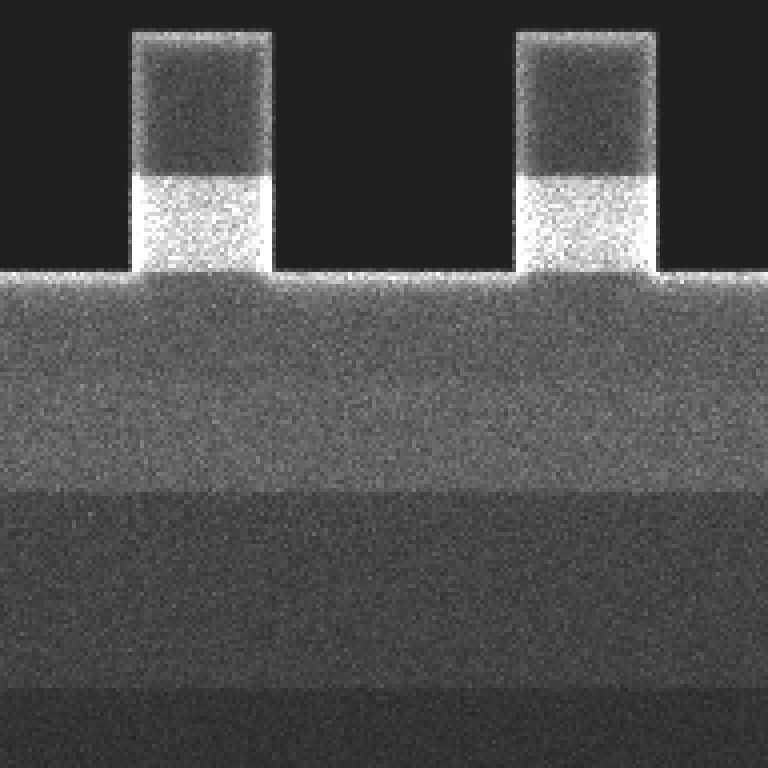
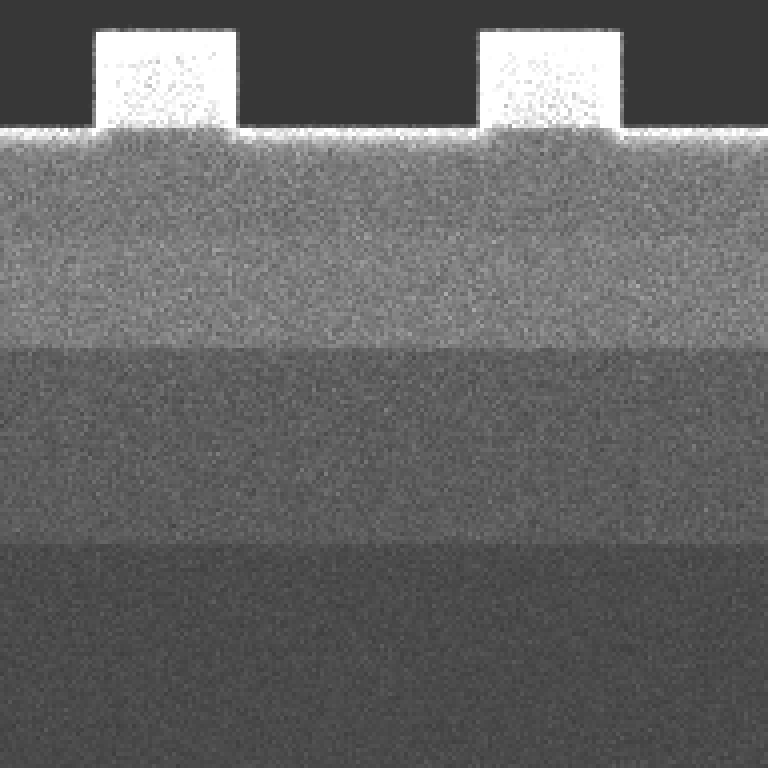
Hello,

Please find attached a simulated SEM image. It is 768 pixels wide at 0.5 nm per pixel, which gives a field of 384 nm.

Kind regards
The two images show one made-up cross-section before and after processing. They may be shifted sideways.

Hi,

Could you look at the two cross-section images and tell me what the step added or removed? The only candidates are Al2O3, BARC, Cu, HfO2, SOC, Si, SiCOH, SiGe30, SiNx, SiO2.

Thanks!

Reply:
removed SOC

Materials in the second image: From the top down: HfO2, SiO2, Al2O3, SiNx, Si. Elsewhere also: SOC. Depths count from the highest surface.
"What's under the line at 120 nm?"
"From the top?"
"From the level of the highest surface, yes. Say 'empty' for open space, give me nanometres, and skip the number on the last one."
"empty 48, SiO2 54, Al2O3 56, SiNx 98, Si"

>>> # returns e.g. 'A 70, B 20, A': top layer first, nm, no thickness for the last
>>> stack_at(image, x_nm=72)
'HfO2 48, SiO2 54, Al2O3 56, SiNx 98, Si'